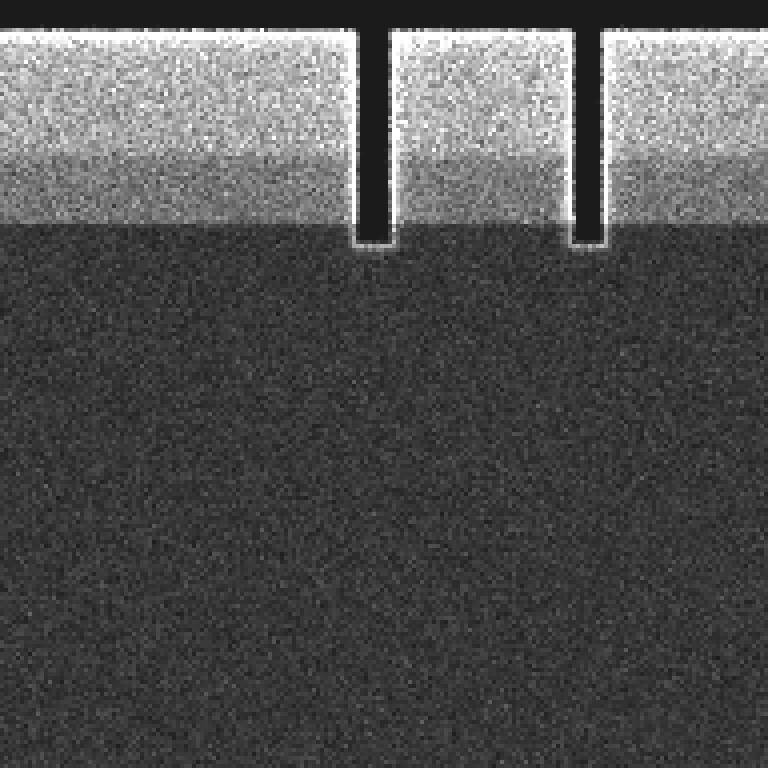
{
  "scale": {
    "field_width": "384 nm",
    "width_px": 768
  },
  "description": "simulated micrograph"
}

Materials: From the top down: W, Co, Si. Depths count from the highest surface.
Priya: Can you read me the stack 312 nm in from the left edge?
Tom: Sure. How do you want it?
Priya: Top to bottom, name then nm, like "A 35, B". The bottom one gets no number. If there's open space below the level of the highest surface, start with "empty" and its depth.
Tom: W 62, Co 34, Si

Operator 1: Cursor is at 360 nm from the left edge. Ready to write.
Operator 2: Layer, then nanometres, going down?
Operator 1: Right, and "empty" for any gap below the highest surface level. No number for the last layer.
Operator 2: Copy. W 62, Co 34, Si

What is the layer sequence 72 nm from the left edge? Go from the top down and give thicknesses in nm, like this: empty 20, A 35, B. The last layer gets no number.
W 62, Co 34, Si